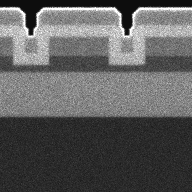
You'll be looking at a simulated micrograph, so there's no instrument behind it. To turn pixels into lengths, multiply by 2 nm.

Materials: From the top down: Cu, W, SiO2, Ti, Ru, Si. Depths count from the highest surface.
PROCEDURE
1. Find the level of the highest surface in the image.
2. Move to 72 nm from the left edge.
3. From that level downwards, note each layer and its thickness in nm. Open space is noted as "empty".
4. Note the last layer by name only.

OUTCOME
empty 38, Cu 52, W 24, Ti 14, Ru 90, Si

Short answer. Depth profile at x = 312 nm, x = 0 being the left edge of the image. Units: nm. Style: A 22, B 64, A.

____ Cu 34, W 24, SiO2 38, Ti 32, Ru 90, Si